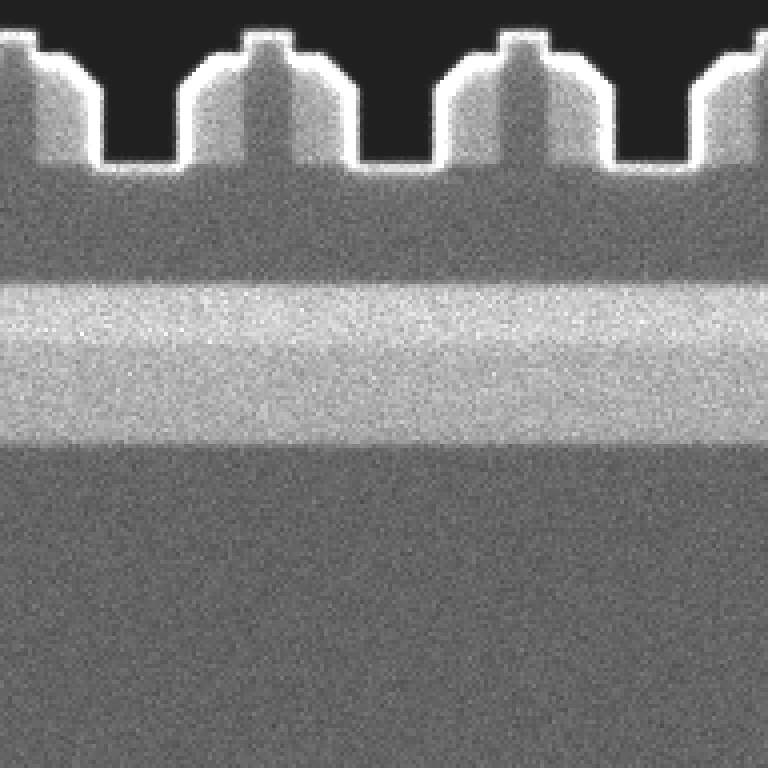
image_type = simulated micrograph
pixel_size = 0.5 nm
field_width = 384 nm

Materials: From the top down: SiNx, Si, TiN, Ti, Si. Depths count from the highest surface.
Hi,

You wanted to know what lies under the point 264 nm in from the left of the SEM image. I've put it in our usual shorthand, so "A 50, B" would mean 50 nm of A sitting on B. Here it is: Si 126, TiN 30, Ti 50, Si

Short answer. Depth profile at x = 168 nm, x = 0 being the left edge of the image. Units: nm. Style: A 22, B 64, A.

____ empty 20, SiNx 46, Si 60, TiN 30, Ti 50, Si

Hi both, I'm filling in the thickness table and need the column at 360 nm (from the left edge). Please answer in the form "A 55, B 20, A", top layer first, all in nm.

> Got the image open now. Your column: empty 14, SiNx 52, Si 60, TiN 30, Ti 50, Si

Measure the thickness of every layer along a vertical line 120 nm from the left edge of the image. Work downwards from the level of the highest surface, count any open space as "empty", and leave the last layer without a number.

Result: empty 12, SiNx 54, Si 60, TiN 30, Ti 50, Si